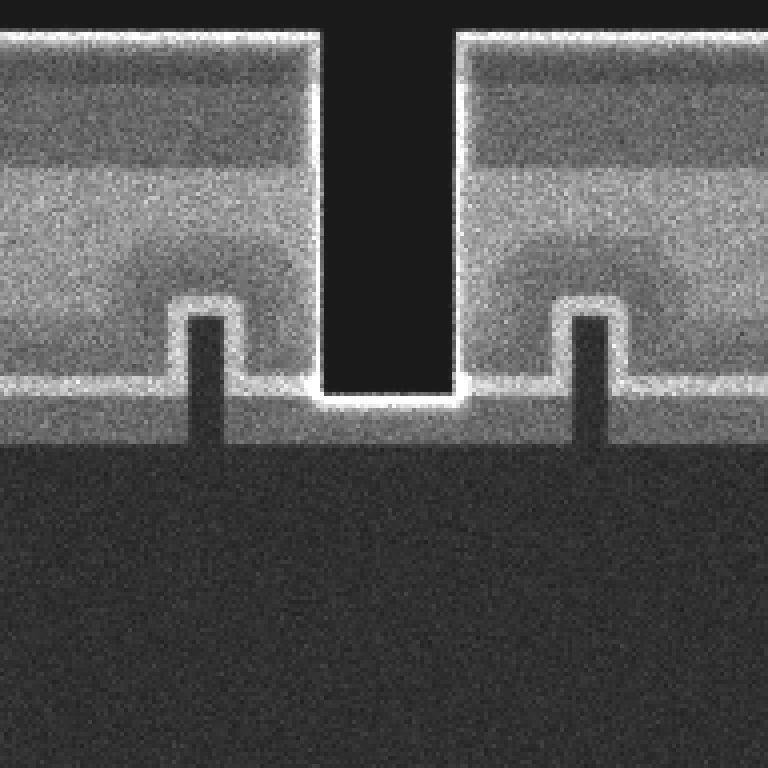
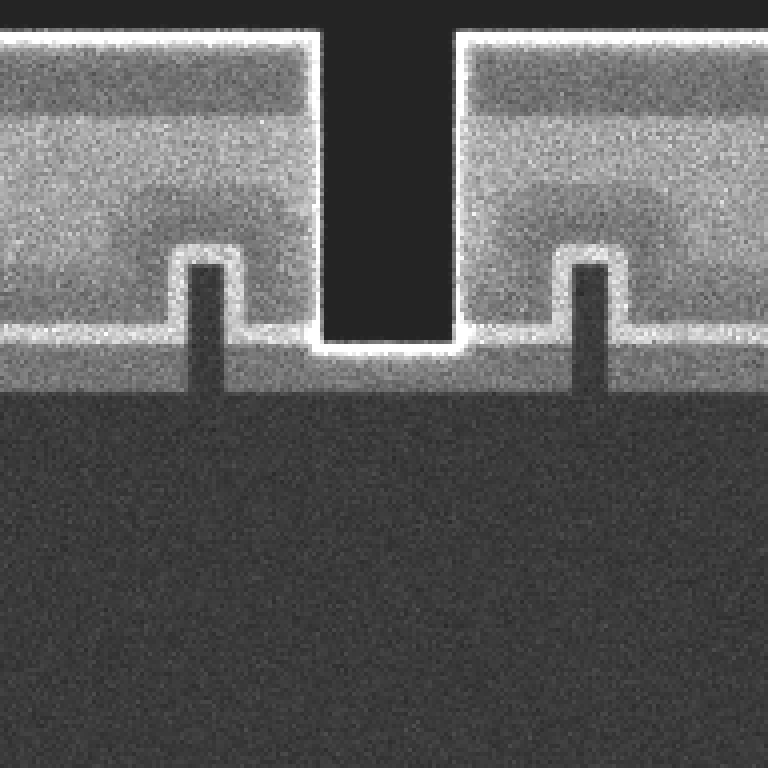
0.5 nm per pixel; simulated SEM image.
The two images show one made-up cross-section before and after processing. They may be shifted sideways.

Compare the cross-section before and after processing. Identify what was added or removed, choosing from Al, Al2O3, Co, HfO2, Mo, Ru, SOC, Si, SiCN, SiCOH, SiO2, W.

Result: SOC removed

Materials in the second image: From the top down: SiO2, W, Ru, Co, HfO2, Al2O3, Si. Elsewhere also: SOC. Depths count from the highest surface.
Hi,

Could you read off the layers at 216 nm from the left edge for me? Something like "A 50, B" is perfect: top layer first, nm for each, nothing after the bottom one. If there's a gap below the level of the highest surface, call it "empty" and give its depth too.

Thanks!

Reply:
empty 156, Al2O3 24, Si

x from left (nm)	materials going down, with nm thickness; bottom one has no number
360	SiO2 42, W 74, Ru 14, Co 16, HfO2 10, Al2O3 24, Si